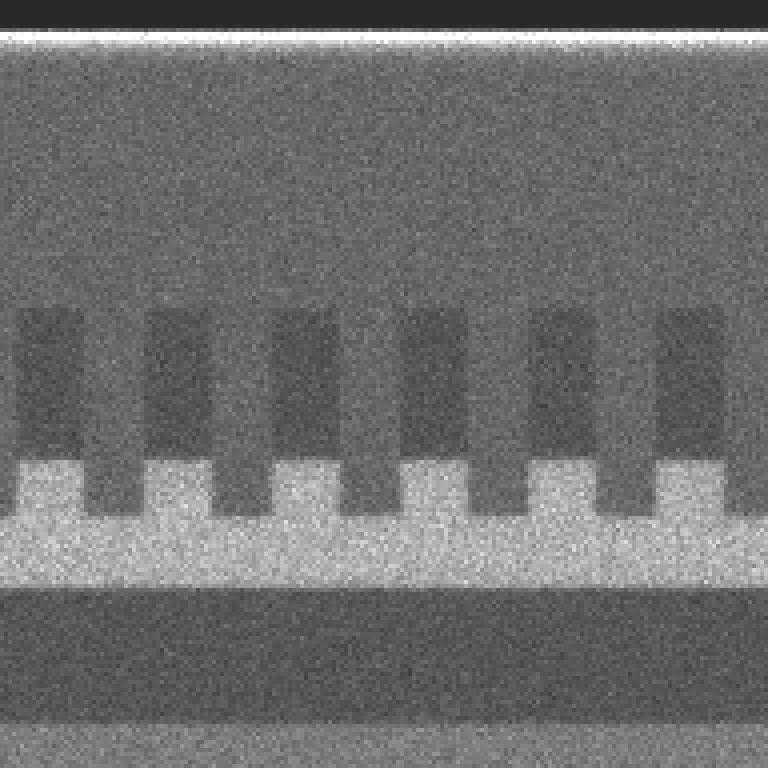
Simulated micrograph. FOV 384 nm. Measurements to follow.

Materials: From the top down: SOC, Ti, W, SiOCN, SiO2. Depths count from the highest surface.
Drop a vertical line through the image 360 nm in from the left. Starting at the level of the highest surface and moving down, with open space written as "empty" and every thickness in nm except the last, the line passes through SOC 138, Ti 76, W 64, SiOCN 68, SiO2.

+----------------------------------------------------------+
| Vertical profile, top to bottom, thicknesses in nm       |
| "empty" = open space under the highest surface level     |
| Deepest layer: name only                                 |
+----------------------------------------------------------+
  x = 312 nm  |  SOC 242, W 36, SiOCN 68, SiO2